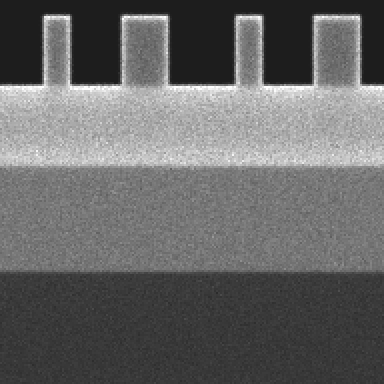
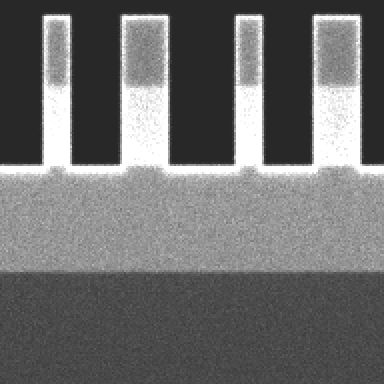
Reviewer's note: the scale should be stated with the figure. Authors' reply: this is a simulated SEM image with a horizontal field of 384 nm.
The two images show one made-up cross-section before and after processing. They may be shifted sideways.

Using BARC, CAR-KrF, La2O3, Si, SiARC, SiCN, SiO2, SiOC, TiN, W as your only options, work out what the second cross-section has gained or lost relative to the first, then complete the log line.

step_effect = removed W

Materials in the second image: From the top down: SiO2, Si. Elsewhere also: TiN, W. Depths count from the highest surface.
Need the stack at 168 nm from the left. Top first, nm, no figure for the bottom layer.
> empty 150, SiO2 106, Si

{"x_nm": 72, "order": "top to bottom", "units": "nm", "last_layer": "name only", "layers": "empty 150, SiO2 106, Si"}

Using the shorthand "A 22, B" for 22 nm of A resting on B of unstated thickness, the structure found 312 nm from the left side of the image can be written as empty 150, SiO2 106, Si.